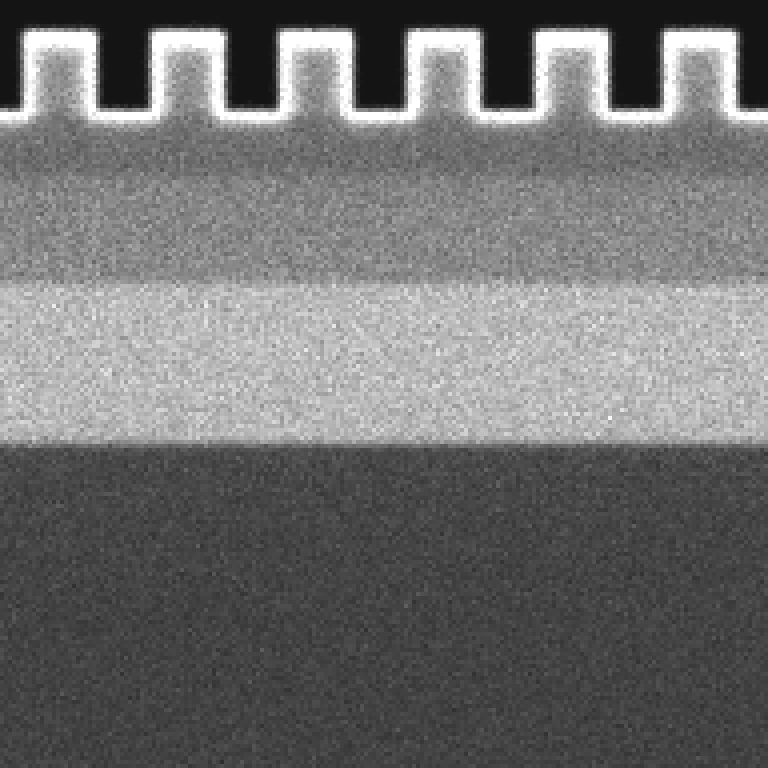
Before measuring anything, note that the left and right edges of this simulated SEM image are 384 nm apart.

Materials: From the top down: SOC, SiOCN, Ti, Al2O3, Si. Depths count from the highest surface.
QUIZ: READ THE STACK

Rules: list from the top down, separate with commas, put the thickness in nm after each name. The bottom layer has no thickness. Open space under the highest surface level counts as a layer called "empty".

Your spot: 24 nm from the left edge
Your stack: SOC 40, SiOCN 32, Ti 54, Al2O3 80, Si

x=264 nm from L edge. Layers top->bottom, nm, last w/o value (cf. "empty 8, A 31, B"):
empty 40, SiOCN 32, Ti 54, Al2O3 80, Si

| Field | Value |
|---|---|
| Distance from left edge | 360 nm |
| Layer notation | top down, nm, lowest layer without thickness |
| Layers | SOC 40, SiOCN 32, Ti 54, Al2O3 80, Si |